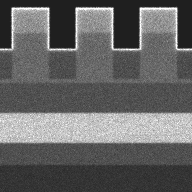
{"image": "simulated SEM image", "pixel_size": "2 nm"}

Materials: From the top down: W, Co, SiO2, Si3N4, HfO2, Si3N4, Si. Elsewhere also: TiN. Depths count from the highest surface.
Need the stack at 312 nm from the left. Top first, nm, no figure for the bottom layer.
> W 50, Co 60, SiO2 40, Si3N4 60, HfO2 60, Si3N4 44, Si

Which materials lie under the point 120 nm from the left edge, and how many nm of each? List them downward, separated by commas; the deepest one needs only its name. empty 82, TiN 60, SiO2 8, Si3N4 60, HfO2 60, Si3N4 44, Si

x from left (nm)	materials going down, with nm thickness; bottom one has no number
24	W 50, Co 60, SiO2 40, Si3N4 60, HfO2 60, Si3N4 44, Si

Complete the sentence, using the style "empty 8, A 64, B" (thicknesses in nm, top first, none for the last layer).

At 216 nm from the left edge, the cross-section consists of W 50, Co 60, SiO2 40, Si3N4 60, HfO2 60, Si3N4 44, Si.